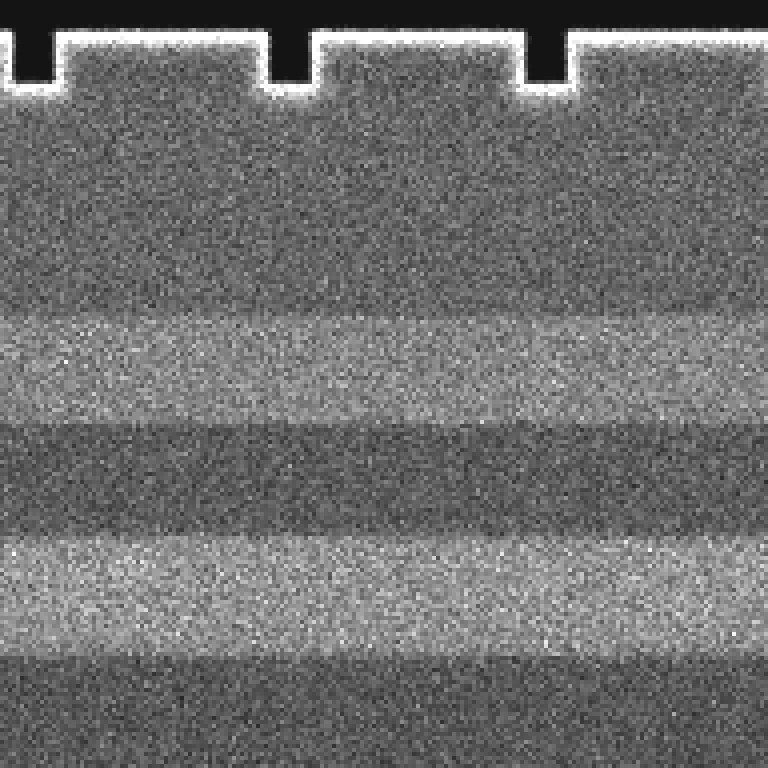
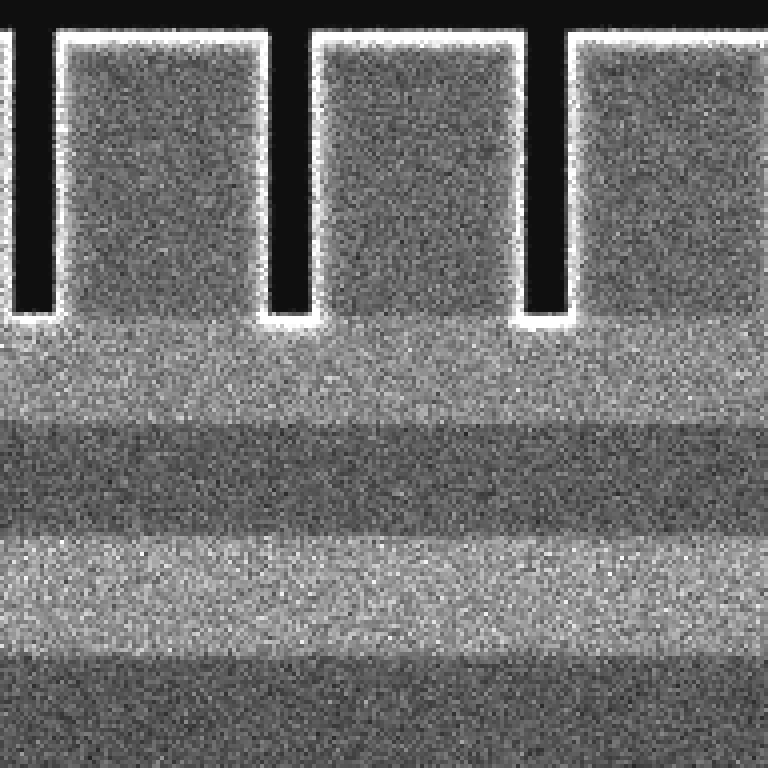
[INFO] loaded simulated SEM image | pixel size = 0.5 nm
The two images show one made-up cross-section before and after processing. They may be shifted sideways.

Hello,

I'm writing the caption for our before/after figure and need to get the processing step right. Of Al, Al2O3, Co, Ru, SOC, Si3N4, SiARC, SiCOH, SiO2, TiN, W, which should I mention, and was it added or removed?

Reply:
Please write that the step removed SOC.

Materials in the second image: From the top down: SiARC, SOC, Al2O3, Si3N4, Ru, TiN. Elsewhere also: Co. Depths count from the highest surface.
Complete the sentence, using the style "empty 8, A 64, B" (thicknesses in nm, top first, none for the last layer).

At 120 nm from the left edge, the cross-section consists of SiARC 26, SOC 116, Al2O3 54, Si3N4 56, Ru 60, TiN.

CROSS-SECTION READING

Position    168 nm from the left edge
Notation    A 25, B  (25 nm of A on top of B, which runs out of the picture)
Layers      SiARC 26, SOC 116, Al2O3 54, Si3N4 56, Ru 60, TiN